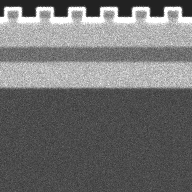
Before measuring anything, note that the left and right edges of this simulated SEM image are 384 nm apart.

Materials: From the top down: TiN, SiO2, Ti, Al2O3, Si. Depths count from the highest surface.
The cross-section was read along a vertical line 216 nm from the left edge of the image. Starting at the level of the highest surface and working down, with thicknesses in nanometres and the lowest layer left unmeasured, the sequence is TiN 20, SiO2 58, Ti 30, Al2O3 52, Si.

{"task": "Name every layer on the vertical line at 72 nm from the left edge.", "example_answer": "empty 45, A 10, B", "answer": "empty 20, SiO2 58, Ti 30, Al2O3 52, Si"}